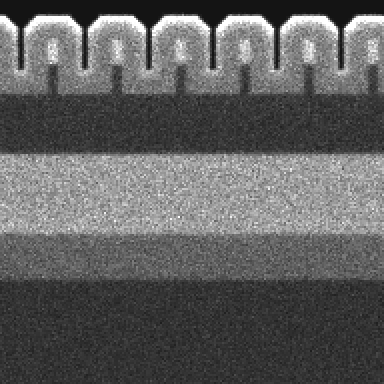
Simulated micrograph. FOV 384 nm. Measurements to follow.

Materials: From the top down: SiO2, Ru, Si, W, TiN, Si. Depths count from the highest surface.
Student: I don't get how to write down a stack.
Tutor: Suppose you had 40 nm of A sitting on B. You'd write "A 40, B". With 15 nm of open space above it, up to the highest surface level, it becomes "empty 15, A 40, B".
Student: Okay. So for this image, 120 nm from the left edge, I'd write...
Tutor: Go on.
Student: SiO2 24, Ru 24, Si 90, W 80, TiN 46, Si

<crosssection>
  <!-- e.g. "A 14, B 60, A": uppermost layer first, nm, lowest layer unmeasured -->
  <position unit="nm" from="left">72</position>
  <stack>empty 4, SiO2 74, Si 60, W 80, TiN 46, Si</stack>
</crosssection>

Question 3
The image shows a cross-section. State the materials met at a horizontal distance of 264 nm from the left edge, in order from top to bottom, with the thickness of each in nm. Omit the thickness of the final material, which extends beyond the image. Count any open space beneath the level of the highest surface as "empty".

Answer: empty 4, SiO2 74, Si 60, W 80, TiN 46, Si